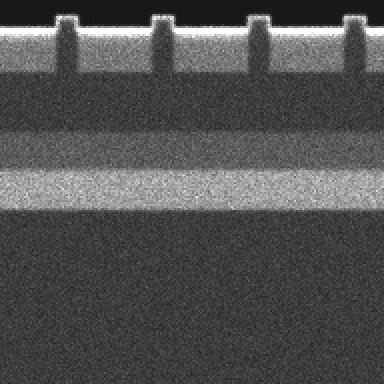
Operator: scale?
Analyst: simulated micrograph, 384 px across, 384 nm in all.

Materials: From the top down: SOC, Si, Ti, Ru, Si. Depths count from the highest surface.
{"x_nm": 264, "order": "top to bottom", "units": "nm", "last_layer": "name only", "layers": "Si 116, Ti 38, Ru 40, Si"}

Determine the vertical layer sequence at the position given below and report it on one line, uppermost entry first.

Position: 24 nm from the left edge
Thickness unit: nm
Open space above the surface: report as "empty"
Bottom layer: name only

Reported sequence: empty 12, SOC 44, Si 60, Ti 38, Ru 40, Si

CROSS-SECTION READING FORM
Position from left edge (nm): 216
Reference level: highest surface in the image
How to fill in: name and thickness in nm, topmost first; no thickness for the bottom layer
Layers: empty 12, SOC 44, Si 60, Ti 38, Ru 40, Si